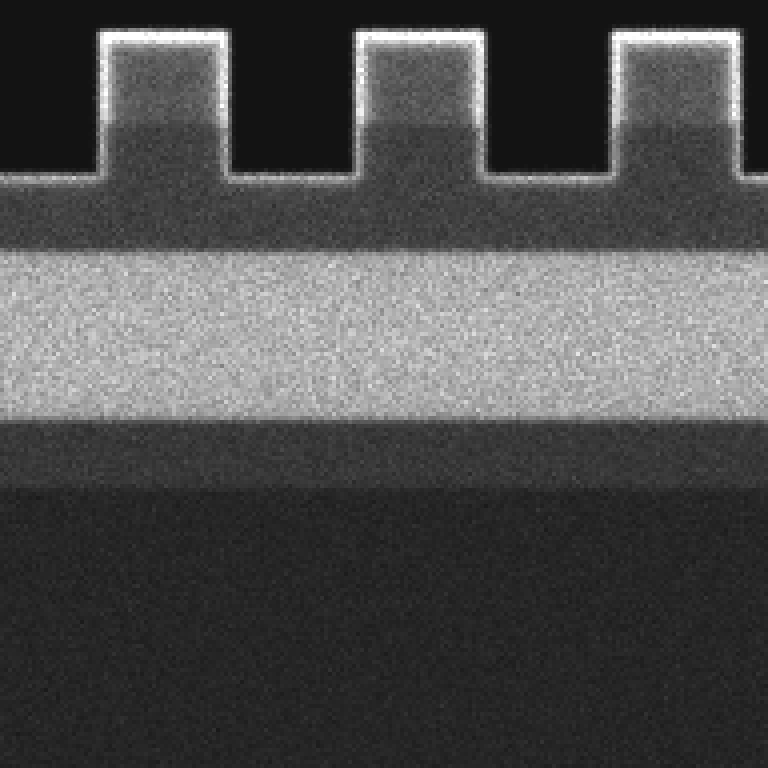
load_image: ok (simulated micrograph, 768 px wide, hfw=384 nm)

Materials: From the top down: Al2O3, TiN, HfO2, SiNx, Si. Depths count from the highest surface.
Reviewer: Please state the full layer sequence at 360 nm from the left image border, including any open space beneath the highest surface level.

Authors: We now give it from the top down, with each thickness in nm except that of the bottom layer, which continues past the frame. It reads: Al2O3 46, TiN 64, HfO2 84, SiNx 34, Si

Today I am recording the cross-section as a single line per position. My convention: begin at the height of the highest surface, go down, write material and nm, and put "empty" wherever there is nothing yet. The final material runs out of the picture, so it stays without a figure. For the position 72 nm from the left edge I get Al2O3 46, TiN 64, HfO2 84, SiNx 34, Si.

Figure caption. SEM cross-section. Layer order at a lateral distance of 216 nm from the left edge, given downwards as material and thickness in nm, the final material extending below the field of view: Al2O3 46, TiN 64, HfO2 84, SiNx 34, Si